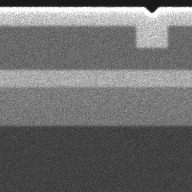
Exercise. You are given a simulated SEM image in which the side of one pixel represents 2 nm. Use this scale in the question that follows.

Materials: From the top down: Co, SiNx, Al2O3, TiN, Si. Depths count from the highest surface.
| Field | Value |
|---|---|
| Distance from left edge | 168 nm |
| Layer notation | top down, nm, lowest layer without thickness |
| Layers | Co 36, SiNx 88, Al2O3 34, TiN 78, Si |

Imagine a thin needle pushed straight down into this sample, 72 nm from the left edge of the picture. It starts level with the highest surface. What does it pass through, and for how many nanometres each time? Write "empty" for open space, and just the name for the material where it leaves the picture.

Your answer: Co 36, SiNx 88, Al2O3 34, TiN 78, Si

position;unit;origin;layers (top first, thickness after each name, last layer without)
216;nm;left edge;Co 36, SiNx 88, Al2O3 34, TiN 78, Si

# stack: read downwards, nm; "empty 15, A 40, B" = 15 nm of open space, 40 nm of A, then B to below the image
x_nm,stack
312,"empty 6, Co 74, SiNx 44, Al2O3 34, TiN 78, Si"